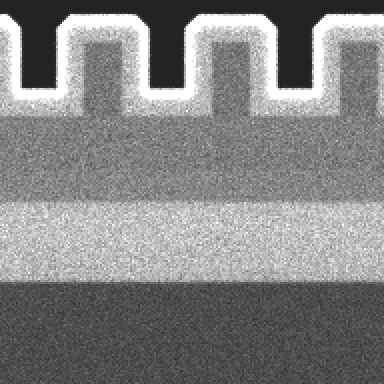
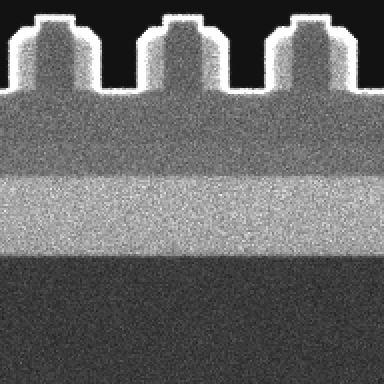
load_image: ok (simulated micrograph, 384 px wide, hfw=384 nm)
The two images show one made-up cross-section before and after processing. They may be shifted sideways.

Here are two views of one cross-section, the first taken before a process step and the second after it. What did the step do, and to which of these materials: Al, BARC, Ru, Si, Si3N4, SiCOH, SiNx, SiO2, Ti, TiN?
It removed SiO2.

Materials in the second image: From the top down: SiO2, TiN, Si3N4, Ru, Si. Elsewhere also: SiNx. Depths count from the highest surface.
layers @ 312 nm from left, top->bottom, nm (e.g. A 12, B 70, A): SiNx 74, TiN 54, Si3N4 32, Ru 80, Si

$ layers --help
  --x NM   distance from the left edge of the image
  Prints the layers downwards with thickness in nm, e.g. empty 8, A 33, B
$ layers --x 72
SiNx 74, TiN 54, Si3N4 32, Ru 80, Si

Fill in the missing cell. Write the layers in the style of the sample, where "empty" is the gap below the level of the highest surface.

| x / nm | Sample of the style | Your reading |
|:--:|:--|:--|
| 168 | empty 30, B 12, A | SiNx 74, TiN 54, Si3N4 32, Ru 80, Si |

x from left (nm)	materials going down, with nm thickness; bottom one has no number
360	empty 74, TiN 54, Si3N4 32, Ru 80, Si